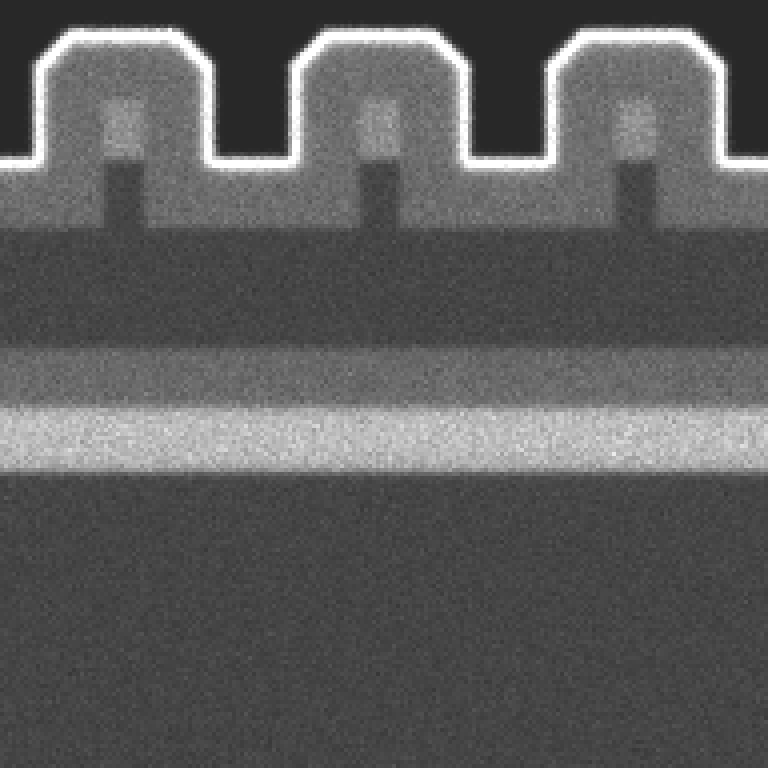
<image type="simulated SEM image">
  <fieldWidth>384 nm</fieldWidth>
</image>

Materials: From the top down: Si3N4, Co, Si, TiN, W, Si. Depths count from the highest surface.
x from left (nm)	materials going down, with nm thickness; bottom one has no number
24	empty 10, Si3N4 88, Si 60, TiN 30, W 32, Si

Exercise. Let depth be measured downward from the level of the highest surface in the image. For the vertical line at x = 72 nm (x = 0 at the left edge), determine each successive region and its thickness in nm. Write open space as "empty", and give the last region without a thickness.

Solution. Si3N4 98, Si 60, TiN 30, W 32, Si